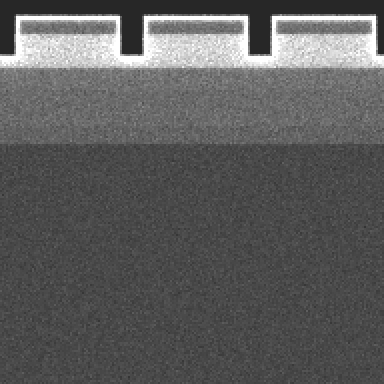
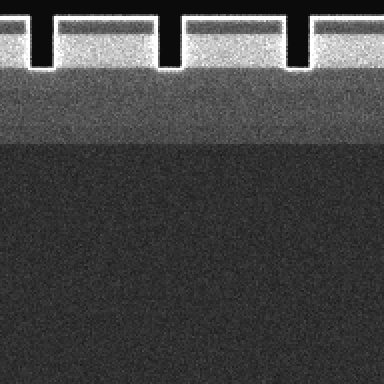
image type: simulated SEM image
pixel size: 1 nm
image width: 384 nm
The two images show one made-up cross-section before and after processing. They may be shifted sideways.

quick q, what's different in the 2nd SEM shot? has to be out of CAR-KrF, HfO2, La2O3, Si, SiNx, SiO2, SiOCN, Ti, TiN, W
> W removed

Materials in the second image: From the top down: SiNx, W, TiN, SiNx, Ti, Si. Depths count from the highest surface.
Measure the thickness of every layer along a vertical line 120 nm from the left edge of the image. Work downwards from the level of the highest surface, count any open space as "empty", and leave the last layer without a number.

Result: SiNx 18, W 34, TiN 22, SiNx 36, Ti 18, Si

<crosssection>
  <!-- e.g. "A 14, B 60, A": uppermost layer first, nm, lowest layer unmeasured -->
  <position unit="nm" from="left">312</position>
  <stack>SiNx 18, W 34, TiN 22, SiNx 36, Ti 18, Si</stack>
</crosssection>